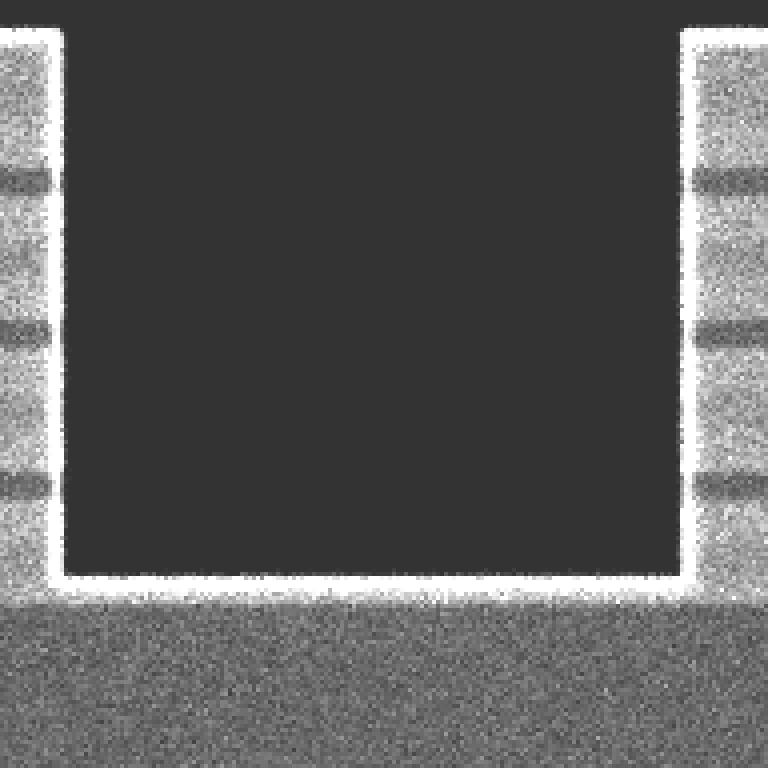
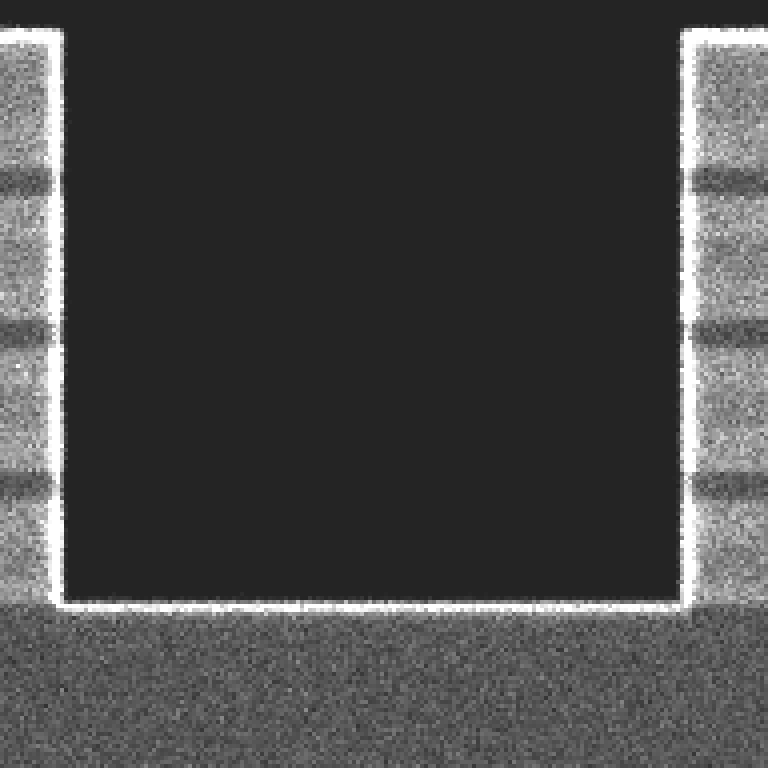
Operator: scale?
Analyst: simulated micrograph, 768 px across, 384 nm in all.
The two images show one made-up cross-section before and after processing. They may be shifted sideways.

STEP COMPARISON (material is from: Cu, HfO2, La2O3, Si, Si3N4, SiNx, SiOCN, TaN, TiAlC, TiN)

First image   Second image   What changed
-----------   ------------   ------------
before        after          TiN, removed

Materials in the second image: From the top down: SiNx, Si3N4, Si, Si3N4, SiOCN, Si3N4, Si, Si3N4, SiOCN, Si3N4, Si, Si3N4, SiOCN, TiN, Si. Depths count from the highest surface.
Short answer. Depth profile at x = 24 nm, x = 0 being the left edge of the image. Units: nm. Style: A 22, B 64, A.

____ SiNx 46, Si3N4 22, Si 14, Si3N4 22, SiOCN 18, Si3N4 22, Si 14, Si3N4 22, SiOCN 18, Si3N4 22, Si 14, Si3N4 22, SiOCN 18, TiN 12, Si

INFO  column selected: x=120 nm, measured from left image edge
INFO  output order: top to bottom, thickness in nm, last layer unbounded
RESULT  empty 286, Si